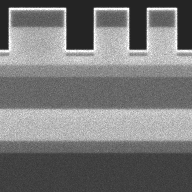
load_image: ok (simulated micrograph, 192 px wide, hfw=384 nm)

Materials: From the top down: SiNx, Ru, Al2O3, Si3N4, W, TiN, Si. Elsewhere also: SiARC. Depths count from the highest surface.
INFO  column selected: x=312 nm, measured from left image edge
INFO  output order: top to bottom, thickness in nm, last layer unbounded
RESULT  SiNx 38, Ru 76, Al2O3 24, Si3N4 64, W 64, TiN 24, Si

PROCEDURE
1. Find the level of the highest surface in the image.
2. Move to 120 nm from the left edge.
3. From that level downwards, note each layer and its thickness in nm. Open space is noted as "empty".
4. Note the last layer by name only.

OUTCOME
SiNx 38, Ru 76, Al2O3 24, Si3N4 64, W 64, TiN 24, Si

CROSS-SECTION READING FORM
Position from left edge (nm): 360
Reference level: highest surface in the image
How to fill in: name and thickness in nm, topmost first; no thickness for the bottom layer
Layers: empty 84, SiARC 12, Ru 18, Al2O3 24, Si3N4 64, W 64, TiN 24, Si